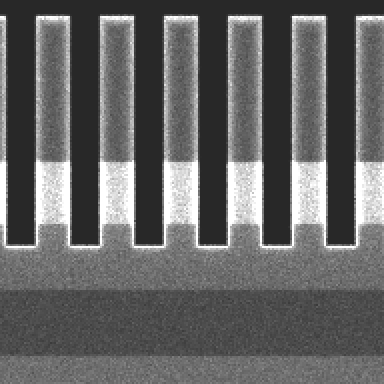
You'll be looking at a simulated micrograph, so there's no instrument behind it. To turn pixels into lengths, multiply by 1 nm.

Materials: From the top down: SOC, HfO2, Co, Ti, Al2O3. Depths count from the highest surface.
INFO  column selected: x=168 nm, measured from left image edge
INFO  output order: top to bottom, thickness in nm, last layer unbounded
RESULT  SOC 146, HfO2 62, Co 66, Ti 66, Al2O3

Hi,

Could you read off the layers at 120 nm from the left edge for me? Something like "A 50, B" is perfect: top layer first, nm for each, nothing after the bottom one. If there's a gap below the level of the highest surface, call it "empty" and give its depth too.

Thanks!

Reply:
SOC 146, HfO2 62, Co 66, Ti 66, Al2O3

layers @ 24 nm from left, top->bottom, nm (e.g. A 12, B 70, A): empty 230, Co 44, Ti 66, Al2O3